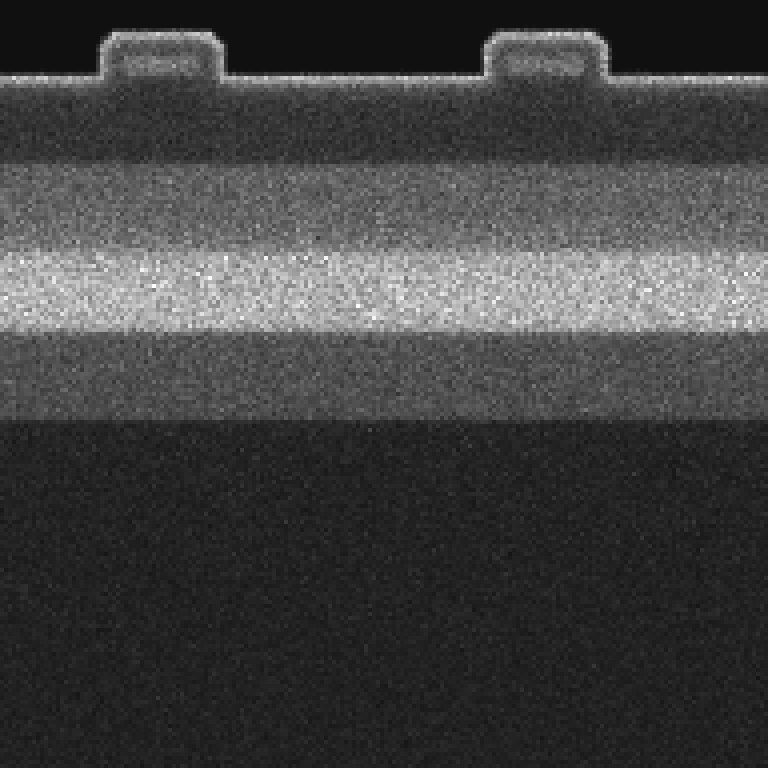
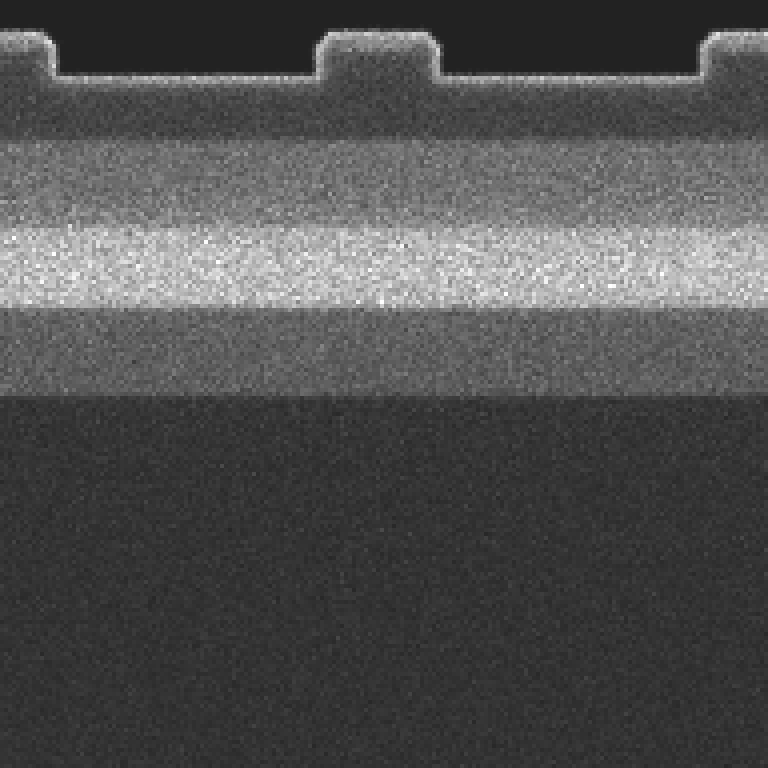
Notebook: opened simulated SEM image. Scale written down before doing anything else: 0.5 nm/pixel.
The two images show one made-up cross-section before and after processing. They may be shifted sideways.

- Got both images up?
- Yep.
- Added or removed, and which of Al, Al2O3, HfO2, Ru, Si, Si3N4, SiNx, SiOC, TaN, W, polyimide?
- removed, Si3N4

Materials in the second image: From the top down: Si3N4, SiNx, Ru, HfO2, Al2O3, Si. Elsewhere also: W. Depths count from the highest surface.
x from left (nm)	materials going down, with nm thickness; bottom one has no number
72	empty 22, SiNx 32, Ru 44, HfO2 40, Al2O3 44, Si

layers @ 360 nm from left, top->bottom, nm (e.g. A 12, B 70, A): Si3N4 22, SiNx 32, Ru 44, HfO2 40, Al2O3 44, Si